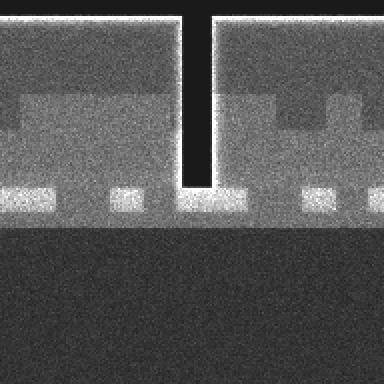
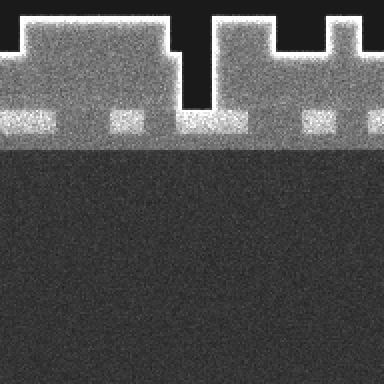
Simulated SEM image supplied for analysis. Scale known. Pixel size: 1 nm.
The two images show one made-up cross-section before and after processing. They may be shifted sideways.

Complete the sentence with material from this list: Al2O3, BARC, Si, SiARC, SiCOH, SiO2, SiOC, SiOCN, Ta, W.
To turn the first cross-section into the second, SiARC must be removed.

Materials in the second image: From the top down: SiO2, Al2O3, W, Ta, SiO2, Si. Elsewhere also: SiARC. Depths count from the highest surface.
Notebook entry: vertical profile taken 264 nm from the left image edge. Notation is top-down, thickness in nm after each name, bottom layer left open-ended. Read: SiO2 78, Al2O3 16, SiO2 40, Si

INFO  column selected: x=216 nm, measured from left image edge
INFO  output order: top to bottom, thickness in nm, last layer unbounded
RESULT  SiO2 78, Al2O3 16, W 18, Ta 6, SiO2 16, Si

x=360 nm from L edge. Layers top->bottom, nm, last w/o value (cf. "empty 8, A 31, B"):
SiO2 78, Al2O3 16, SiO2 40, Si